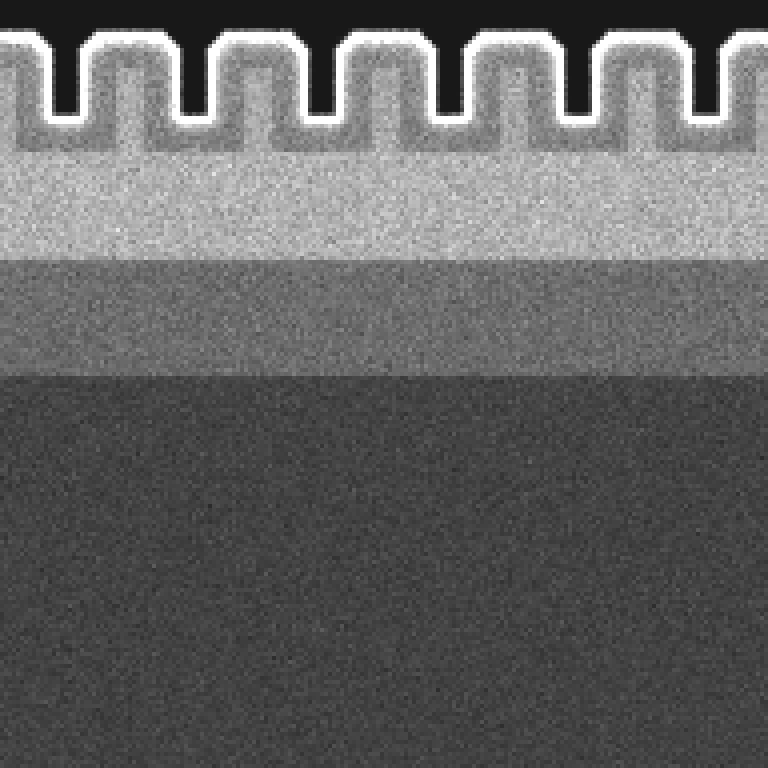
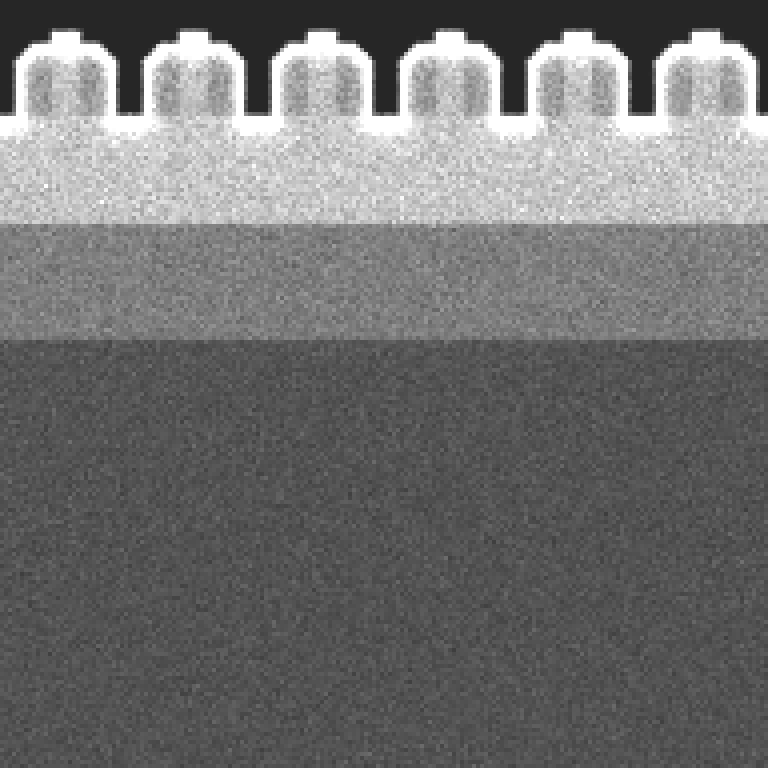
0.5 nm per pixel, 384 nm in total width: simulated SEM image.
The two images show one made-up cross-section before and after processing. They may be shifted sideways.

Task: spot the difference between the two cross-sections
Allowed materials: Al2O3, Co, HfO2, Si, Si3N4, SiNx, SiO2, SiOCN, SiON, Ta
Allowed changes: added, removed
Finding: removed Si3N4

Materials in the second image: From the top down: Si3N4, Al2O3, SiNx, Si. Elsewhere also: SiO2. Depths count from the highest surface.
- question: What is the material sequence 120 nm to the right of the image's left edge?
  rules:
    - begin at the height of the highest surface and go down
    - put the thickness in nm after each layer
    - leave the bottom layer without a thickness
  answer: empty 14, Si3N4 28, Al2O3 54, SiNx 58, Si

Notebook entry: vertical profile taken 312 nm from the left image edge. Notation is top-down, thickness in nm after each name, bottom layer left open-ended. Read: empty 14, Si3N4 28, Al2O3 54, SiNx 58, Si